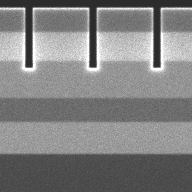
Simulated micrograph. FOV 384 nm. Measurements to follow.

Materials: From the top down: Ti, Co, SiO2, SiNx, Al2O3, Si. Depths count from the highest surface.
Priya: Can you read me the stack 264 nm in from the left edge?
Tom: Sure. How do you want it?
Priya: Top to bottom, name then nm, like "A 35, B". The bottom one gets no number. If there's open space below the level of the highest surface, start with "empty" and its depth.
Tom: Ti 48, Co 58, SiO2 74, SiNx 48, Al2O3 64, Si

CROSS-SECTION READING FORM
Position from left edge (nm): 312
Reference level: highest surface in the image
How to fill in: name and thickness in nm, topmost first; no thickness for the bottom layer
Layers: empty 120, SiO2 60, SiNx 48, Al2O3 64, Si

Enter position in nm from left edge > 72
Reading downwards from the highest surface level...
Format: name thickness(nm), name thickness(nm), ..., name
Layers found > Ti 48, Co 58, SiO2 74, SiNx 48, Al2O3 64, Si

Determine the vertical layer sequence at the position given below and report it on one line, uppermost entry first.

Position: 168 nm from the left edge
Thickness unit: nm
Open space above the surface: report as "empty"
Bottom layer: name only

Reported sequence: Ti 48, Co 58, SiO2 74, SiNx 48, Al2O3 64, Si